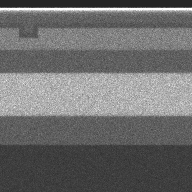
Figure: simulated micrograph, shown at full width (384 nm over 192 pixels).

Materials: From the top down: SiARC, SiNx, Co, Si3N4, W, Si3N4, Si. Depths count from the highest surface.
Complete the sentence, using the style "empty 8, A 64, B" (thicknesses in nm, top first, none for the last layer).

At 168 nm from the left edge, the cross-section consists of SiARC 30, SiNx 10, Co 44, Si3N4 46, W 86, Si3N4 58, Si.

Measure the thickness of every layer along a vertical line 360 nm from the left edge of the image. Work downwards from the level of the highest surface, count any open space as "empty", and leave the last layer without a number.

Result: SiARC 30, SiNx 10, Co 44, Si3N4 46, W 86, Si3N4 58, Si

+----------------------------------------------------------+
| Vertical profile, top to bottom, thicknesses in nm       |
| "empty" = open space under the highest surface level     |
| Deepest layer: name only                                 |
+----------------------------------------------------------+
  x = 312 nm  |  SiARC 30, SiNx 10, Co 44, Si3N4 46, W 86, Si3N4 58, Si